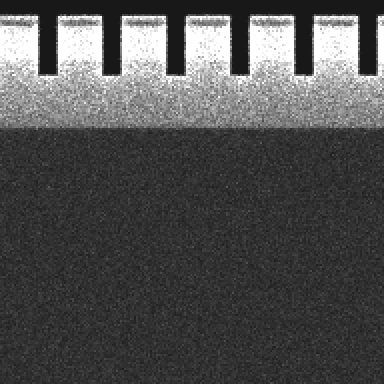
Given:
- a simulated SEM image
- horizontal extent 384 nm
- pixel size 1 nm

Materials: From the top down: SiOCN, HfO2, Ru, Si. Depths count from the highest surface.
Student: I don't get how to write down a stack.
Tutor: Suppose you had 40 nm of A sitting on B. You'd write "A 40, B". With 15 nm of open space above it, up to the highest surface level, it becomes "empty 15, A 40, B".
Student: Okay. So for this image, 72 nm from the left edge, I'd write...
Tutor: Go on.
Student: SiOCN 10, HfO2 34, Ru 68, Si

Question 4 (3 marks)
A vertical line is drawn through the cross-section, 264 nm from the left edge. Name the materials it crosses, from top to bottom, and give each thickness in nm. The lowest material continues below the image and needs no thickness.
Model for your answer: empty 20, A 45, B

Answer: SiOCN 10, HfO2 34, Ru 68, Si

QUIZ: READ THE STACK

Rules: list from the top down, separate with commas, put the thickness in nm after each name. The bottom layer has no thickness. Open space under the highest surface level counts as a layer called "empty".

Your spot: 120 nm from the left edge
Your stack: empty 60, Ru 52, Si